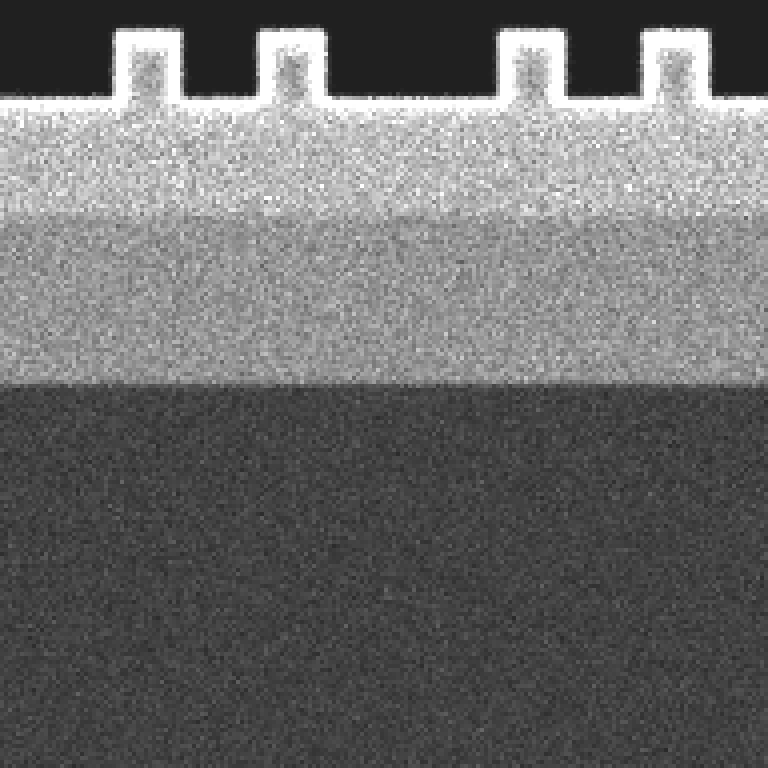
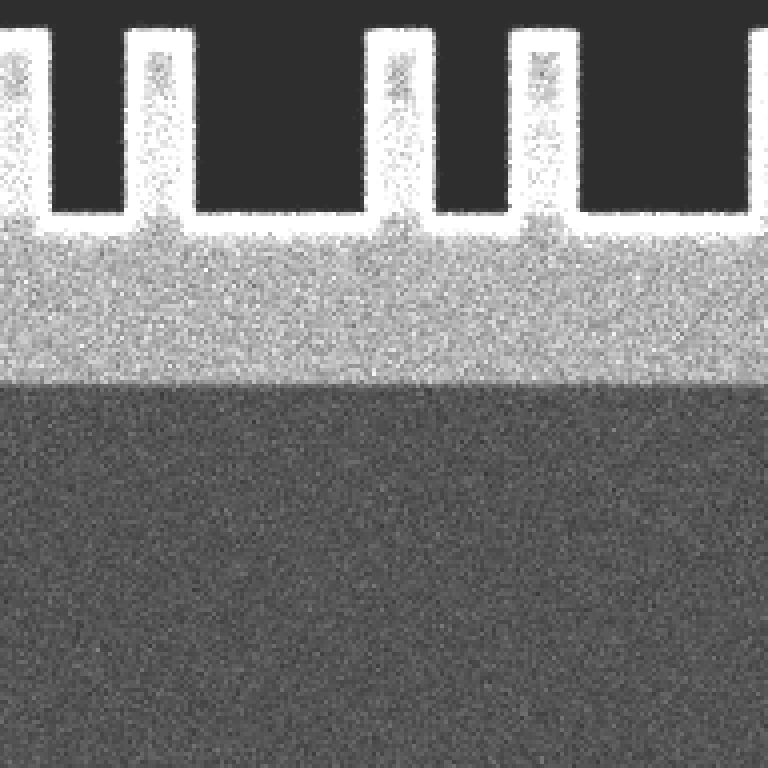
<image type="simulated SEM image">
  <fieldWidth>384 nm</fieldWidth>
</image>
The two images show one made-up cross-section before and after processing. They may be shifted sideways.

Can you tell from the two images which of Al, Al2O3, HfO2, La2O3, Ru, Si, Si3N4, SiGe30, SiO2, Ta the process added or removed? Yes, it removed Ru.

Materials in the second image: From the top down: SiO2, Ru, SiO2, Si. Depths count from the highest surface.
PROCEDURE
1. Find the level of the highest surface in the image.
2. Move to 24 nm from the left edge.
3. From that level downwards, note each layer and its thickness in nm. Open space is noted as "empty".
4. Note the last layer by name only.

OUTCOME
empty 92, SiO2 84, Si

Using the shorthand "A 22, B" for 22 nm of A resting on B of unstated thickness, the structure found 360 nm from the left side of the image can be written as empty 92, SiO2 84, Si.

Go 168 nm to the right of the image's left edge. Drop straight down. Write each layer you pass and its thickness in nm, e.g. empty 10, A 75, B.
empty 92, SiO2 84, Si